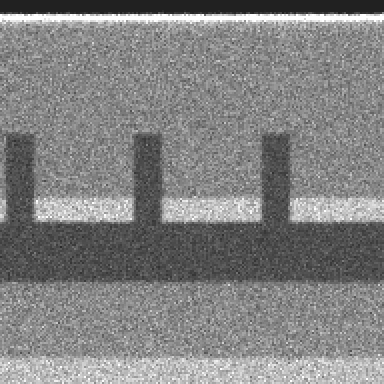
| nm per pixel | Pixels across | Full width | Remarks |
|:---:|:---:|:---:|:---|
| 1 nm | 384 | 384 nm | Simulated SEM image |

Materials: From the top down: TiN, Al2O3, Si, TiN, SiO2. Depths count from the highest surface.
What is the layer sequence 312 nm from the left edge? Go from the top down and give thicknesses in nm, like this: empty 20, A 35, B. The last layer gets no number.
TiN 182, Al2O3 24, Si 60, TiN 76, SiO2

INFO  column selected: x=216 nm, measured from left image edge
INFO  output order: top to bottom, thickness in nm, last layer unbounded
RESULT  TiN 182, Al2O3 24, Si 60, TiN 76, SiO2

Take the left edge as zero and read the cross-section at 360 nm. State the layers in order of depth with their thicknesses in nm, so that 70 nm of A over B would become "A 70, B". TiN 182, Al2O3 24, Si 60, TiN 76, SiO2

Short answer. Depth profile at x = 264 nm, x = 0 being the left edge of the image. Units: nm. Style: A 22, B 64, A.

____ TiN 118, Si 148, TiN 76, SiO2